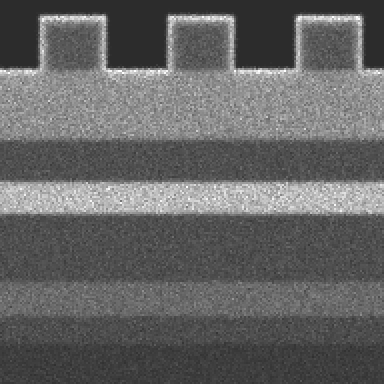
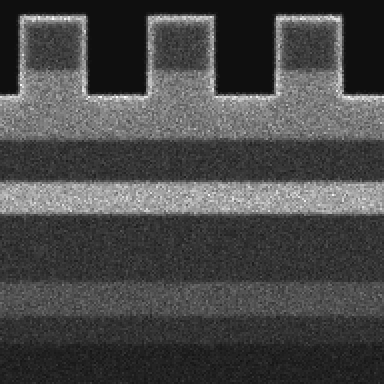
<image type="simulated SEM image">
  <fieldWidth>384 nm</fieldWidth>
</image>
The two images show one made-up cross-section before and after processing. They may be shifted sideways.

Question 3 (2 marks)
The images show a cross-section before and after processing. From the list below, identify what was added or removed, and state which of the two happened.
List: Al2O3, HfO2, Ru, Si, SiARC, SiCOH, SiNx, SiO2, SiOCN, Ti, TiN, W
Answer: W was removed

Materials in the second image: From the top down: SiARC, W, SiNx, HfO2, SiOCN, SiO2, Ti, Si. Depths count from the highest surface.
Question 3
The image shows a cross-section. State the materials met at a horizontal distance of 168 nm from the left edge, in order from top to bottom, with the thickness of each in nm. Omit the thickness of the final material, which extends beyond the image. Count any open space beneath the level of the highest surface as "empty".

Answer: SiARC 54, W 70, SiNx 42, HfO2 32, SiOCN 68, SiO2 34, Ti 28, Si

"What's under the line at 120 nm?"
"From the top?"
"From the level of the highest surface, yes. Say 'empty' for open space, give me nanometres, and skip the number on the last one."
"empty 80, W 44, SiNx 42, HfO2 32, SiOCN 68, SiO2 34, Ti 28, Si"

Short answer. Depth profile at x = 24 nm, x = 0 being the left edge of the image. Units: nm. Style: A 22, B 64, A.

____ SiARC 54, W 70, SiNx 42, HfO2 32, SiOCN 68, SiO2 34, Ti 28, Si